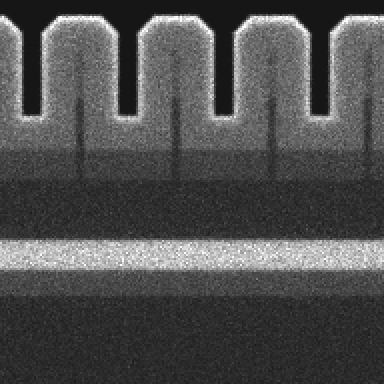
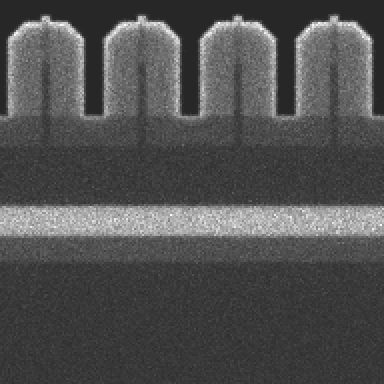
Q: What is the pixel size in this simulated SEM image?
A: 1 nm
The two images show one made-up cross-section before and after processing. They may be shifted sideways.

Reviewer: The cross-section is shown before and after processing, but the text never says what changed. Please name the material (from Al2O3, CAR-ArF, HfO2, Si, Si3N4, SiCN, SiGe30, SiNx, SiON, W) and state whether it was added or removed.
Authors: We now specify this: Al2O3, removed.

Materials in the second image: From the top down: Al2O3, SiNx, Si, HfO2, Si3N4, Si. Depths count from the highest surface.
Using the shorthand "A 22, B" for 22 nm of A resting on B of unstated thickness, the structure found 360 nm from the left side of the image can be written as empty 12, Al2O3 88, SiNx 30, Si 60, HfO2 30, Si3N4 26, Si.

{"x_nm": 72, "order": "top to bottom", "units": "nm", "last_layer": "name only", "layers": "empty 12, Al2O3 88, SiNx 30, Si 60, HfO2 30, Si3N4 26, Si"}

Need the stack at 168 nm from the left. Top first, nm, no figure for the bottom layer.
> empty 12, Al2O3 88, SiNx 30, Si 60, HfO2 30, Si3N4 26, Si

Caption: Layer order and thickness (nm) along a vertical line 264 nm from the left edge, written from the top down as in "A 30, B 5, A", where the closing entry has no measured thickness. empty 12, Al2O3 88, SiNx 30, Si 60, HfO2 30, Si3N4 26, Si